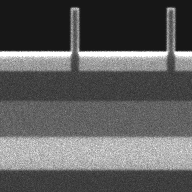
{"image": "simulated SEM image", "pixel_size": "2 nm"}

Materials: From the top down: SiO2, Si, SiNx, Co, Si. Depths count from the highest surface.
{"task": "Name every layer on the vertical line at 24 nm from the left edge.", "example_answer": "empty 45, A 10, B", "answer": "empty 88, SiO2 38, Si 60, SiNx 72, Co 66, Si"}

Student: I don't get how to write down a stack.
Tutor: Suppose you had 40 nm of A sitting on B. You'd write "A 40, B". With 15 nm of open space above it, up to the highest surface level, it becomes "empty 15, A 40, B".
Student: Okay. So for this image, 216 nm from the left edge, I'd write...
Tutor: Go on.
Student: empty 88, SiO2 38, Si 60, SiNx 72, Co 66, Si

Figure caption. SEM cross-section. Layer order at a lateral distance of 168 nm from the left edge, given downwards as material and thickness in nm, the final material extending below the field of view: empty 88, SiO2 38, Si 60, SiNx 72, Co 66, Si